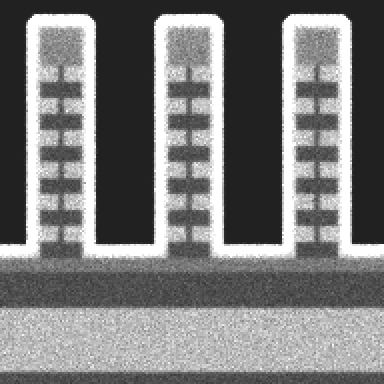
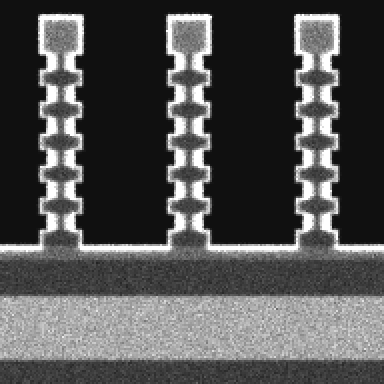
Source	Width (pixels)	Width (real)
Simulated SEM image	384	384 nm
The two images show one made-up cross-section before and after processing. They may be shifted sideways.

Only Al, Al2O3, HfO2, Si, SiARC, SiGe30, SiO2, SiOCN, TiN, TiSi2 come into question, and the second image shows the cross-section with Al2O3 removed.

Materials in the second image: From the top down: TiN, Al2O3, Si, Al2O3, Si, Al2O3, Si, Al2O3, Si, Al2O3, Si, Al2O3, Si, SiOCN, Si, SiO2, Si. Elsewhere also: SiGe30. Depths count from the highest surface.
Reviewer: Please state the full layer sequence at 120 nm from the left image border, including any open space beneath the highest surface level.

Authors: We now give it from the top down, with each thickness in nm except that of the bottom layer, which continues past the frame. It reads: empty 230, SiOCN 14, Si 36, SiO2 64, Si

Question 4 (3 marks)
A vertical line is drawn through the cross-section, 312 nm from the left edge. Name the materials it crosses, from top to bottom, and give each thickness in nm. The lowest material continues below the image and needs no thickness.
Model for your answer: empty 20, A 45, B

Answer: TiN 38, Al2O3 16, Si 16, Al2O3 16, Si 16, Al2O3 16, Si 16, Al2O3 16, Si 16, Al2O3 16, Si 16, Al2O3 16, Si 16, SiOCN 14, Si 36, SiO2 64, Si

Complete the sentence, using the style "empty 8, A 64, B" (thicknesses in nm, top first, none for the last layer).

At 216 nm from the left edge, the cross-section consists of empty 230, SiOCN 14, Si 36, SiO2 64, Si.